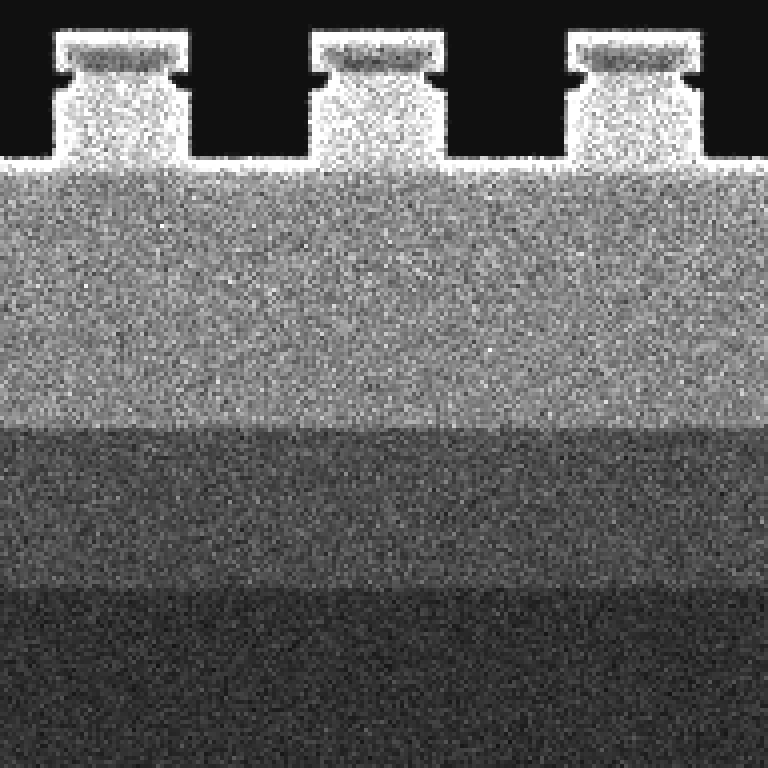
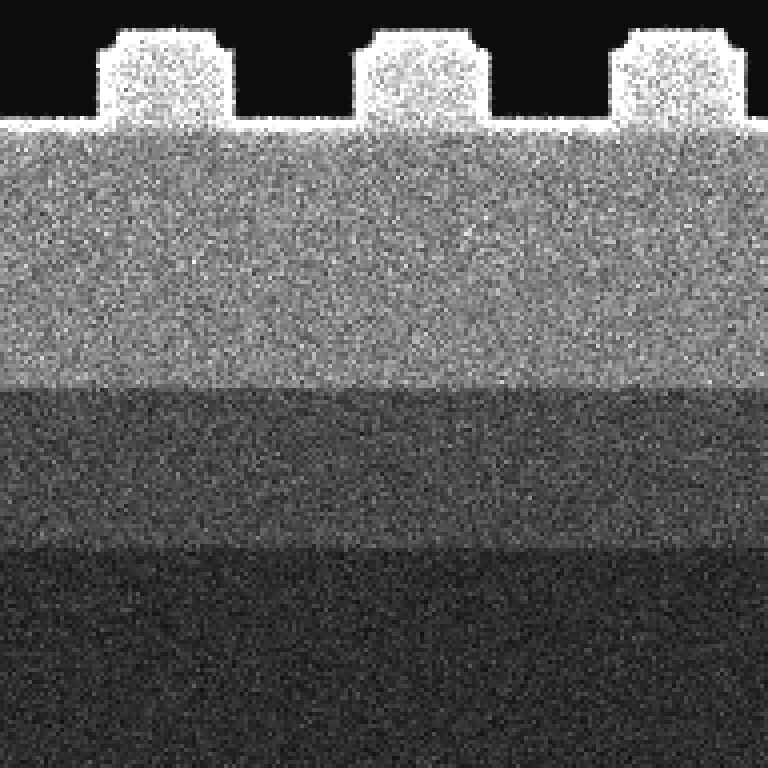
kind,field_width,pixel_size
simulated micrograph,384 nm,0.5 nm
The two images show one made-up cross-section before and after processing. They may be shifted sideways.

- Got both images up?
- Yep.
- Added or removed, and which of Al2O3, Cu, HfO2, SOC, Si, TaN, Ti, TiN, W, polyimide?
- removed, SOC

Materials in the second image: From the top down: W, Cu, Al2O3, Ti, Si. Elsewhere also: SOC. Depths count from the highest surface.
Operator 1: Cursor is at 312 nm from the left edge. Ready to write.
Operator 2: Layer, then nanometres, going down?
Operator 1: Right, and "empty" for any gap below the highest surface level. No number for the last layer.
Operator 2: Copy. empty 8, W 42, Cu 72, Al2O3 56, Ti 80, Si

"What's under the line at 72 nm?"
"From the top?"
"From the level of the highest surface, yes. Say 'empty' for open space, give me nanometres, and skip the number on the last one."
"W 50, Cu 72, Al2O3 56, Ti 80, Si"